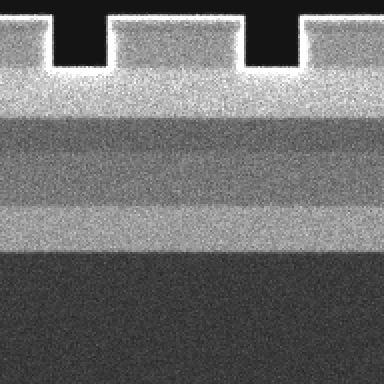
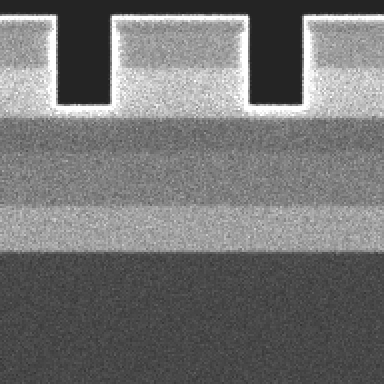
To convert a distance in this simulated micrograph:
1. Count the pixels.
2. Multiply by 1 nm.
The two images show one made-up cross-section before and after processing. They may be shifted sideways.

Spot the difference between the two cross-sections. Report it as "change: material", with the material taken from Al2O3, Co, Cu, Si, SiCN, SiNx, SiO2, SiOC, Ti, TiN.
removed: Co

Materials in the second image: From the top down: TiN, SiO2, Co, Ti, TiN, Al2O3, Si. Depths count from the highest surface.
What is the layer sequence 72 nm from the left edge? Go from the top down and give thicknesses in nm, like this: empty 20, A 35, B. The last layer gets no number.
empty 90, Co 12, Ti 34, TiN 54, Al2O3 46, Si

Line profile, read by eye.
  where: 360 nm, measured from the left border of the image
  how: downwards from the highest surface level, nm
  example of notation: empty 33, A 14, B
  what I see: TiN 16, SiO2 36, Co 50, Ti 34, TiN 54, Al2O3 46, Si